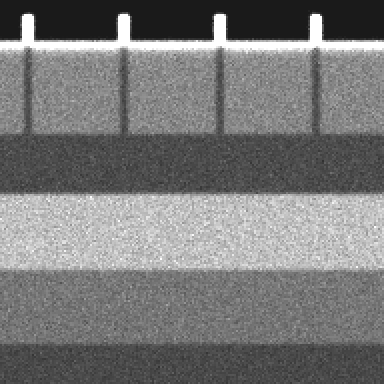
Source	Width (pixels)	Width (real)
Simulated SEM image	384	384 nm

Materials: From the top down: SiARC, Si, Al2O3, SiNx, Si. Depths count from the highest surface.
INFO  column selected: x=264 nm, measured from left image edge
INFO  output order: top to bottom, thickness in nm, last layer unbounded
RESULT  empty 26, SiARC 92, Si 60, Al2O3 76, SiNx 74, Si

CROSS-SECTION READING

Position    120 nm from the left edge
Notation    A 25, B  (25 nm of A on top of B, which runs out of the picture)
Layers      SiARC 28, Si 150, Al2O3 76, SiNx 74, Si